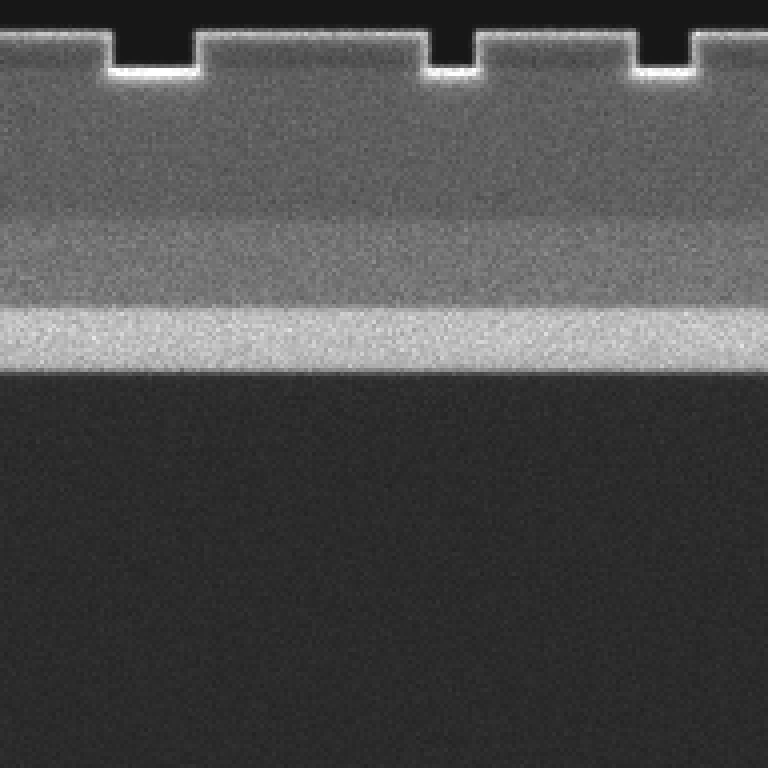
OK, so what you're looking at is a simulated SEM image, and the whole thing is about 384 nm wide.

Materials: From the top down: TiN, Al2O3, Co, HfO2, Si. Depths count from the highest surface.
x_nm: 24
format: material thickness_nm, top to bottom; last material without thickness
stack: TiN 18, Al2O3 76, Co 44, HfO2 32, Si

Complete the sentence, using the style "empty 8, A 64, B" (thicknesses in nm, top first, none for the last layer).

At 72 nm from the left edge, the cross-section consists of empty 18, Al2O3 76, Co 44, HfO2 32, Si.